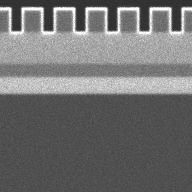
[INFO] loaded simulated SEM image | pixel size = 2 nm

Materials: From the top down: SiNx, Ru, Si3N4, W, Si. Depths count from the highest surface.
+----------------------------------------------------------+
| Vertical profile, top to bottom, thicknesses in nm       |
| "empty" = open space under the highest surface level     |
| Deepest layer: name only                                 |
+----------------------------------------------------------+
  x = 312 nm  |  SiNx 48, Ru 64, Si3N4 26, W 34, Si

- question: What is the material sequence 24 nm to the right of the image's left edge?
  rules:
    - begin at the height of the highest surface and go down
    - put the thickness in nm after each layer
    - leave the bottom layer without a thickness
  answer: empty 48, Ru 64, Si3N4 26, W 34, Si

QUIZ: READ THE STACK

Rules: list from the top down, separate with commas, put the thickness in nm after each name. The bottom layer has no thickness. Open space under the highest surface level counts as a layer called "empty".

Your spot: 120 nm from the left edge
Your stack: SiNx 48, Ru 64, Si3N4 26, W 34, Si